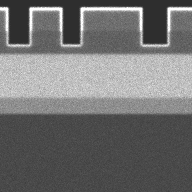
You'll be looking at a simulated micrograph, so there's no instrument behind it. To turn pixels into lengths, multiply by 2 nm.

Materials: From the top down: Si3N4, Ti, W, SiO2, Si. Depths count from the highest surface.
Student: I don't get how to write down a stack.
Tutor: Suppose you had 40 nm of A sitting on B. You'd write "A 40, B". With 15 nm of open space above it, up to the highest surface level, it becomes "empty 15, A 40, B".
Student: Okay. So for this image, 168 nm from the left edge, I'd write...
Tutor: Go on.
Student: Si3N4 46, Ti 46, W 88, SiO2 32, Si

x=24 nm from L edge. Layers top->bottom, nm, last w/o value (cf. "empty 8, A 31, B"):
empty 74, Ti 18, W 88, SiO2 32, Si